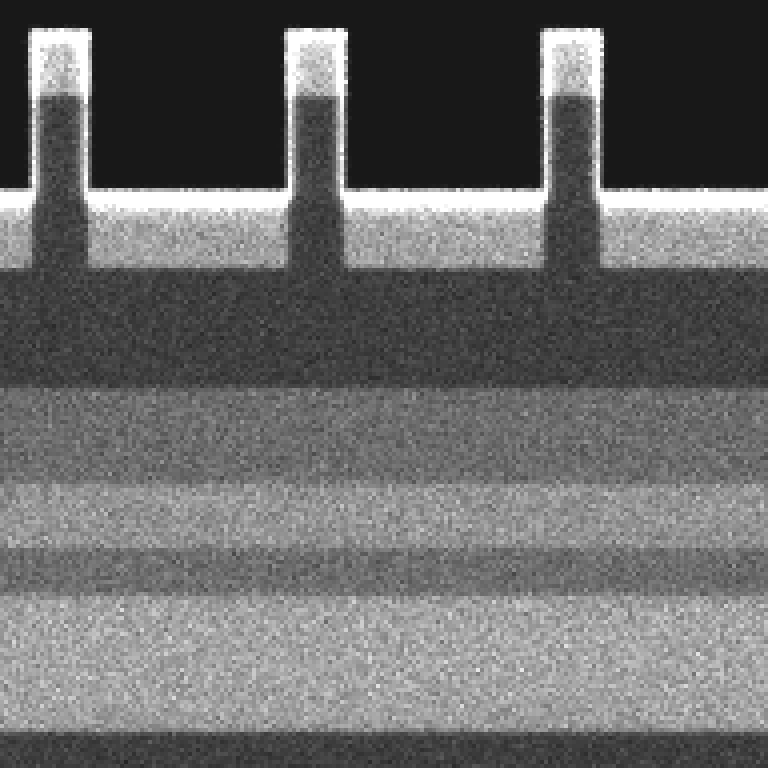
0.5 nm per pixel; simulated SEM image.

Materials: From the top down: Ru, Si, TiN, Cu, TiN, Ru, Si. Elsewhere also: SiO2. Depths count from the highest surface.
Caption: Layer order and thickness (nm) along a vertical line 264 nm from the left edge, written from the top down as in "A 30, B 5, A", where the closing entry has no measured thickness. empty 80, SiO2 38, Si 60, TiN 48, Cu 32, TiN 24, Ru 68, Si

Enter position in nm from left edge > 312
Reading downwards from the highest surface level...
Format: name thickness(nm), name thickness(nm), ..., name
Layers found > empty 80, SiO2 38, Si 60, TiN 48, Cu 32, TiN 24, Ru 68, Si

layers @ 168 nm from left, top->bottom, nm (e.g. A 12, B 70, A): Ru 32, Si 146, TiN 48, Cu 32, TiN 24, Ru 68, Si